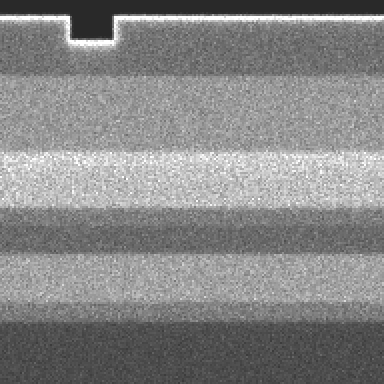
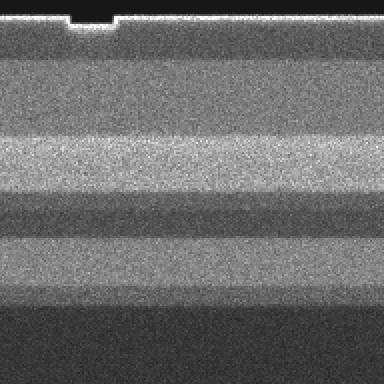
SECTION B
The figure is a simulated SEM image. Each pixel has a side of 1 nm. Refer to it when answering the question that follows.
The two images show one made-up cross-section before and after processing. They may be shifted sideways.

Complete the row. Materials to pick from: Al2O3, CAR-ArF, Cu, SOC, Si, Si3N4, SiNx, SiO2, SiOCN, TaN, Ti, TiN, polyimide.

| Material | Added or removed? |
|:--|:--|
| SiNx | removed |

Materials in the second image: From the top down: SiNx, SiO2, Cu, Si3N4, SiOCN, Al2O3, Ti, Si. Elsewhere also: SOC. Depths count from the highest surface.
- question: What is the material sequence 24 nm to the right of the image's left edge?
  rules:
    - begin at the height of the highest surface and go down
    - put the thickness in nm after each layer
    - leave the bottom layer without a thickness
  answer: SiNx 44, SiO2 76, Cu 56, Si3N4 18, SiOCN 28, Al2O3 48, Ti 20, Si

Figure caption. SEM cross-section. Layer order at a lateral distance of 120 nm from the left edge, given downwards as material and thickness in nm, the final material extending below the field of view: SiNx 44, SiO2 76, Cu 56, Si3N4 18, SiOCN 28, Al2O3 48, Ti 20, Si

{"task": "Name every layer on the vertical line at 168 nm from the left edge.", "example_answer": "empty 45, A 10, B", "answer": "SiNx 44, SiO2 76, Cu 56, Si3N4 18, SiOCN 28, Al2O3 48, Ti 20, Si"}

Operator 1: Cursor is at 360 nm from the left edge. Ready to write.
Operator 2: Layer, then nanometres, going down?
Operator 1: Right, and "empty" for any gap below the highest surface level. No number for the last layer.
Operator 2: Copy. SiNx 44, SiO2 76, Cu 56, Si3N4 18, SiOCN 28, Al2O3 48, Ti 20, Si